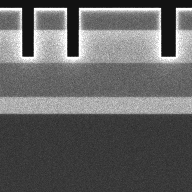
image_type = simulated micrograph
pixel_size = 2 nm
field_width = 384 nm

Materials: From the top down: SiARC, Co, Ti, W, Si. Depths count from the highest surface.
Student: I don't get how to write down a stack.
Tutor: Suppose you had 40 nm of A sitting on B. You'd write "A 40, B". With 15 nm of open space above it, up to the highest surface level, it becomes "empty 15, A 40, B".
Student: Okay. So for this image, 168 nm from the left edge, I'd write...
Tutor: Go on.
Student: SiARC 44, Co 66, Ti 68, W 34, Si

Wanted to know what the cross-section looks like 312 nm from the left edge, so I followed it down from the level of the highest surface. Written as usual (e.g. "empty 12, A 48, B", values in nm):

SiARC 44, Co 66, Ti 68, W 34, Si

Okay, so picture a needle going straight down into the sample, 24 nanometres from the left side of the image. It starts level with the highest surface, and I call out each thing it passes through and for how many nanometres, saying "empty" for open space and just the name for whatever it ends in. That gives SiARC 44, Co 66, Ti 68, W 34, Si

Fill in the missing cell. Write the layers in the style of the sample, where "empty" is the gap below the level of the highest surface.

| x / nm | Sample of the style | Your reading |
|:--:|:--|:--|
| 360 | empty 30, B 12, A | SiARC 44, Co 66, Ti 68, W 34, Si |